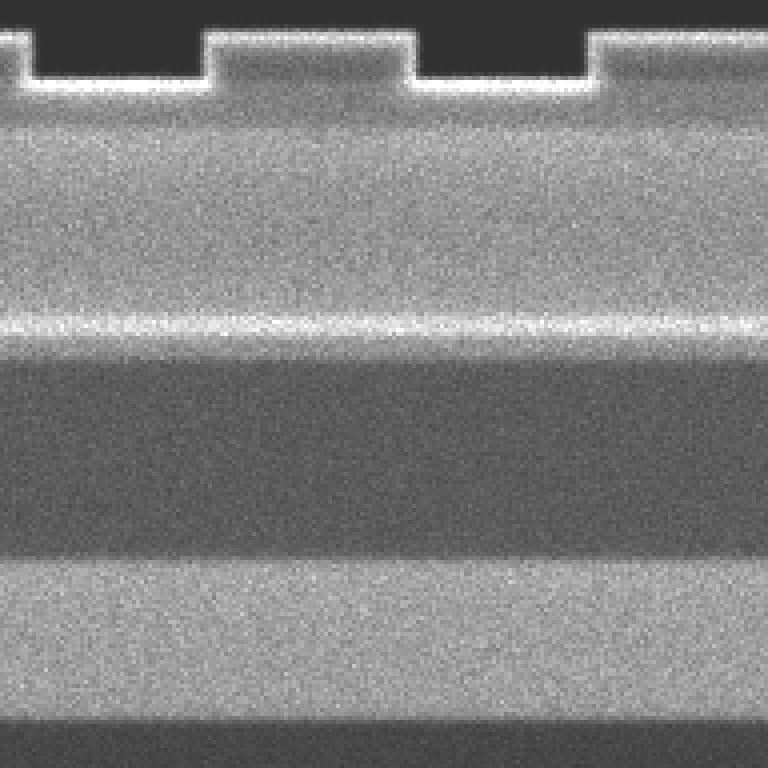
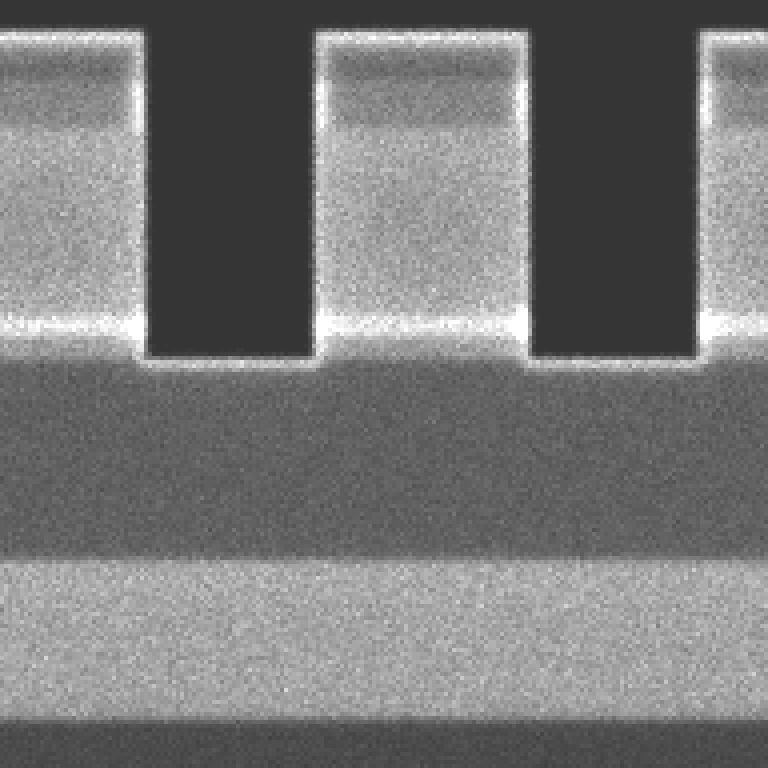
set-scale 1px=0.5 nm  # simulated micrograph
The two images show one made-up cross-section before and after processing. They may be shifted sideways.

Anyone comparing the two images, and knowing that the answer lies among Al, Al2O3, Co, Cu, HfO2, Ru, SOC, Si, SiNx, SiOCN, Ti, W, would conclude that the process removed Al2O3 and Co and HfO2 and Ru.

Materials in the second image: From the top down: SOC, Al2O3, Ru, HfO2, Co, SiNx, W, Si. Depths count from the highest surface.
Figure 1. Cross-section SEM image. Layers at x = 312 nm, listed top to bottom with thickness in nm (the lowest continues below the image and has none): empty 164, SiNx 100, W 80, Si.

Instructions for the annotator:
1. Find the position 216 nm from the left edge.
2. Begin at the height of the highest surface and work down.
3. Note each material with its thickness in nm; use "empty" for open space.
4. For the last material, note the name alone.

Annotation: SOC 24, Al2O3 24, Ru 94, HfO2 10, Co 12, SiNx 100, W 80, Si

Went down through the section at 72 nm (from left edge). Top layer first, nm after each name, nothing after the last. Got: empty 164, SiNx 100, W 80, Si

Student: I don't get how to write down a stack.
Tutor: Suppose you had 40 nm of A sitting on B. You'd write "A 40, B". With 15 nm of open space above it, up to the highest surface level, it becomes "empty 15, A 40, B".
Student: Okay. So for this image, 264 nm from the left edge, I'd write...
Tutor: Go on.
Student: empty 164, SiNx 100, W 80, Si